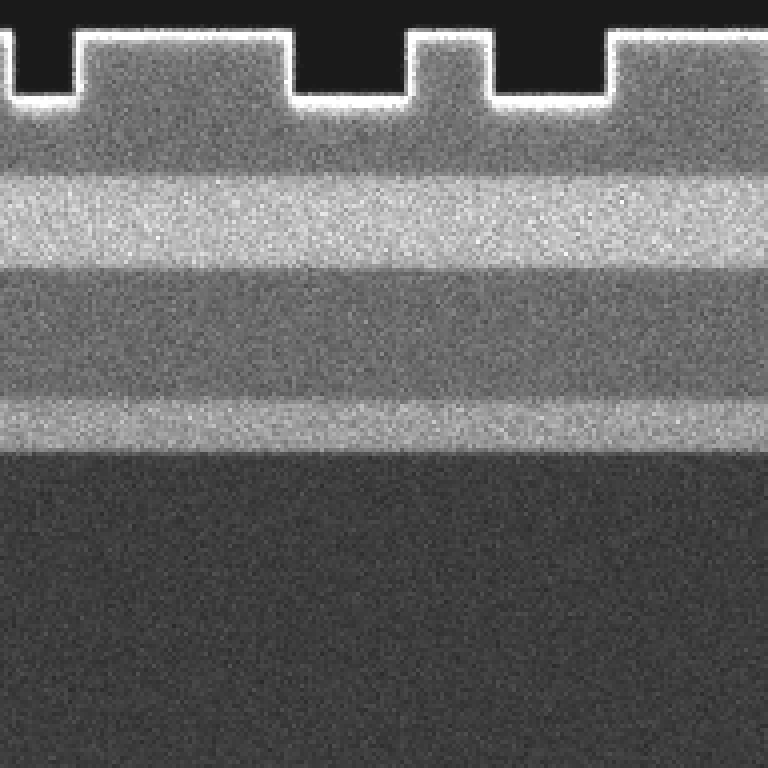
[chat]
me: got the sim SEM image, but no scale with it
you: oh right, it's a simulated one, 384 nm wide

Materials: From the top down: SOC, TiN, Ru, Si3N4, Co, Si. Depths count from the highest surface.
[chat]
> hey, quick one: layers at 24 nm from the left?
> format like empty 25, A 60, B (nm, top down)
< empty 32, SOC 8, TiN 32, Ru 46, Si3N4 66, Co 26, Si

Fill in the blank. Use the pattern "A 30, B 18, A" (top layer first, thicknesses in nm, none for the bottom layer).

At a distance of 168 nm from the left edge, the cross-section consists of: empty 32, SOC 8, TiN 32, Ru 46, Si3N4 66, Co 26, Si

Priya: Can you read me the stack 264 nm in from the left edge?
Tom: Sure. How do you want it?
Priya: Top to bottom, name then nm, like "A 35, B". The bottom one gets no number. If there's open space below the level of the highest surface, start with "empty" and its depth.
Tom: empty 32, SOC 8, TiN 32, Ru 46, Si3N4 66, Co 26, Si